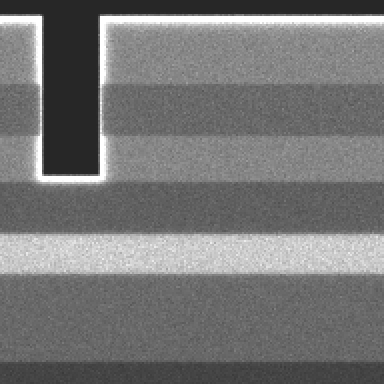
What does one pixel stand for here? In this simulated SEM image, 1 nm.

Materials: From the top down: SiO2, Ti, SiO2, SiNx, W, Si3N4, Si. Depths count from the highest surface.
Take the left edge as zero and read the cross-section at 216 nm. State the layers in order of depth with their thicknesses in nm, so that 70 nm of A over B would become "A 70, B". SiO2 68, Ti 52, SiO2 46, SiNx 52, W 40, Si3N4 88, Si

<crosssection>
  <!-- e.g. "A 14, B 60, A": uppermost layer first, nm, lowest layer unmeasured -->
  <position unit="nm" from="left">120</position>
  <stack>SiO2 68, Ti 52, SiO2 46, SiNx 52, W 40, Si3N4 88, Si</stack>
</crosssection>